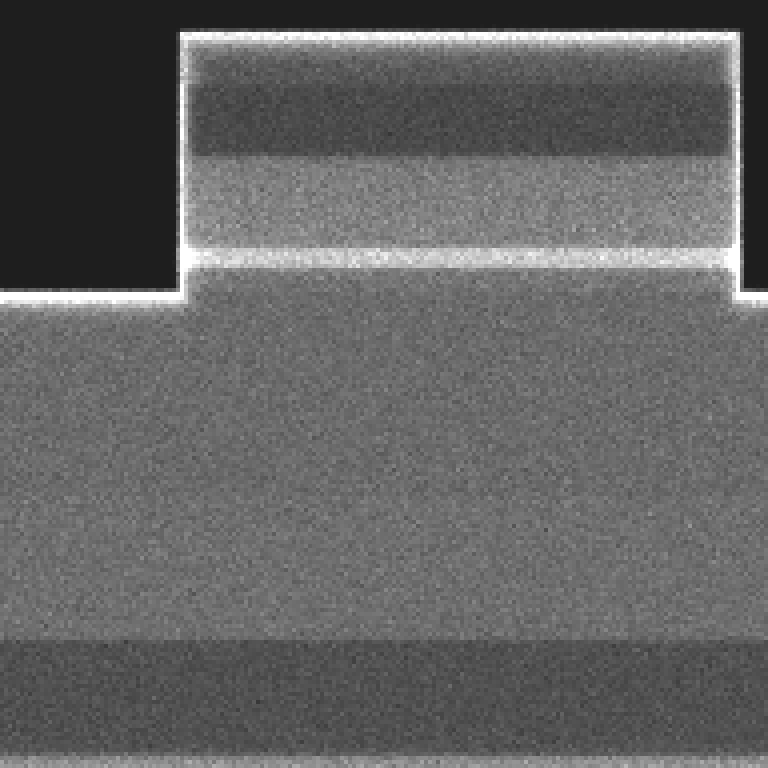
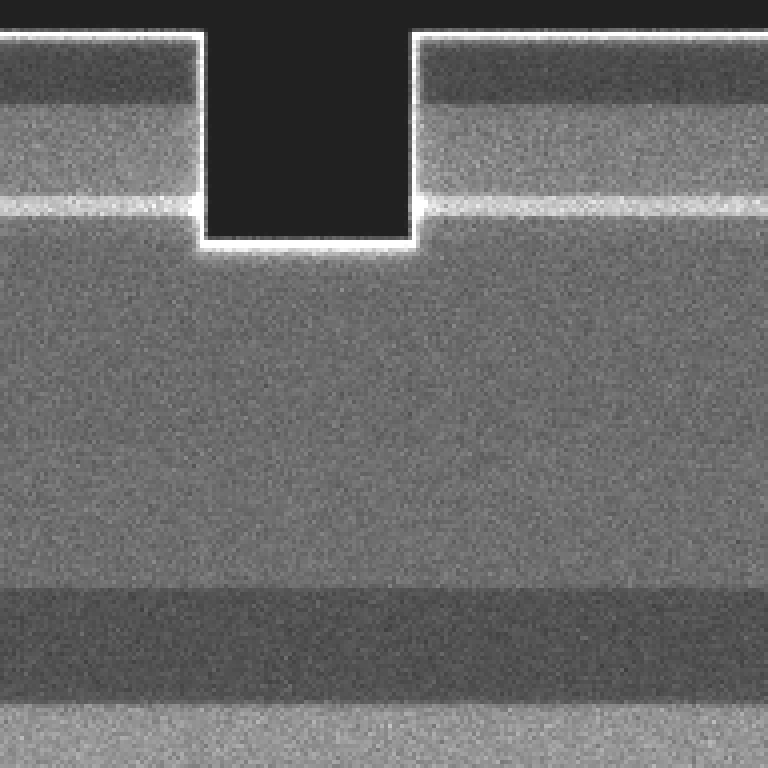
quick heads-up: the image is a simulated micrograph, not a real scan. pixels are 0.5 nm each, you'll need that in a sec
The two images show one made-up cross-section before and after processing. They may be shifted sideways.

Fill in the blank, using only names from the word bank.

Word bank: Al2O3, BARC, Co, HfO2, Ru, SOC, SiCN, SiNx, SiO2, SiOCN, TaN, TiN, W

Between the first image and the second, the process removed SOC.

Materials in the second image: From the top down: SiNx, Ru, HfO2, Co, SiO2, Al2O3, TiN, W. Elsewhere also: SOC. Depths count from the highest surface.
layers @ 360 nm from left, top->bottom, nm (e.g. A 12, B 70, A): SiNx 36, Ru 46, HfO2 10, Co 12, SiO2 102, Al2O3 72, TiN 58, W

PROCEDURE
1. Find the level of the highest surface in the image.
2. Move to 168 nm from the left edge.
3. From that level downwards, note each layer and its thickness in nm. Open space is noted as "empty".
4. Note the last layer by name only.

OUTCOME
empty 104, SiO2 102, Al2O3 72, TiN 58, W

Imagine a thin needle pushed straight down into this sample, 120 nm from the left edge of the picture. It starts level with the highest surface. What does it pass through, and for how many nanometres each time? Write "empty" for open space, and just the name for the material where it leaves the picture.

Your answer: empty 104, SiO2 102, Al2O3 72, TiN 58, W